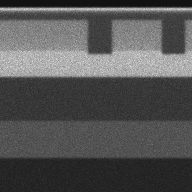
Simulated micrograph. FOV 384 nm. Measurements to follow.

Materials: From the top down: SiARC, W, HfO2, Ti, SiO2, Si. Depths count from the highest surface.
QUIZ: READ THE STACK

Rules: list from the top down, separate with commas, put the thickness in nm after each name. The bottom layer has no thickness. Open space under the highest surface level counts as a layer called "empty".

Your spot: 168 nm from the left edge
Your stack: SiARC 24, W 62, HfO2 52, Ti 88, SiO2 74, Si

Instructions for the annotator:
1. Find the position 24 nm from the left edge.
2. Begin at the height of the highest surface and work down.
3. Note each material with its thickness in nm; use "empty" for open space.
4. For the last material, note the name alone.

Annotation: SiARC 24, W 62, HfO2 52, Ti 88, SiO2 74, Si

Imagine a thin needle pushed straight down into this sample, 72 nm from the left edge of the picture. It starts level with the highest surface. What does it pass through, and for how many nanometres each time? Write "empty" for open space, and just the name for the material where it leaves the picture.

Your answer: SiARC 24, W 62, HfO2 52, Ti 88, SiO2 74, Si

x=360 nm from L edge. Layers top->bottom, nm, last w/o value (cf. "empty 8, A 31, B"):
SiARC 92, HfO2 46, Ti 88, SiO2 74, Si